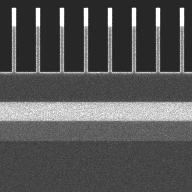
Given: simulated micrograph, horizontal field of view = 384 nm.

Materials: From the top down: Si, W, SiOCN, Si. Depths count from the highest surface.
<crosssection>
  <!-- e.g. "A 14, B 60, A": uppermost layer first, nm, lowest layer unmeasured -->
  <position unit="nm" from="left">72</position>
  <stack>Si 188, W 38, SiOCN 40, Si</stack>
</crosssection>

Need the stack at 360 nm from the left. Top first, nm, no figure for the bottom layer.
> Si 188, W 38, SiOCN 40, Si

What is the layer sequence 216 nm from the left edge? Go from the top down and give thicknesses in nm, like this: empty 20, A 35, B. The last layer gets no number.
Si 188, W 38, SiOCN 40, Si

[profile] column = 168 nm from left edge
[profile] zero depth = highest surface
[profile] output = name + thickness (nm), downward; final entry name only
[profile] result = Si 188, W 38, SiOCN 40, Si